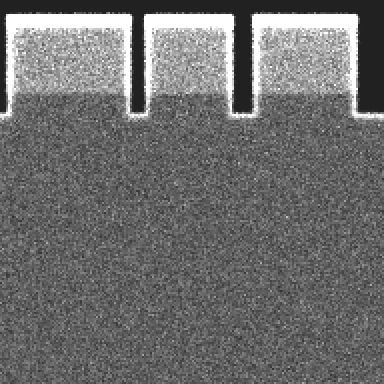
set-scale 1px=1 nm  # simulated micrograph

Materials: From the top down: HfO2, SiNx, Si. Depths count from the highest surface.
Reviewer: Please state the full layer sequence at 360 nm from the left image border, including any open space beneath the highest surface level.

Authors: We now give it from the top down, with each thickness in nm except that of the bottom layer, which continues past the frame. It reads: empty 98, Si